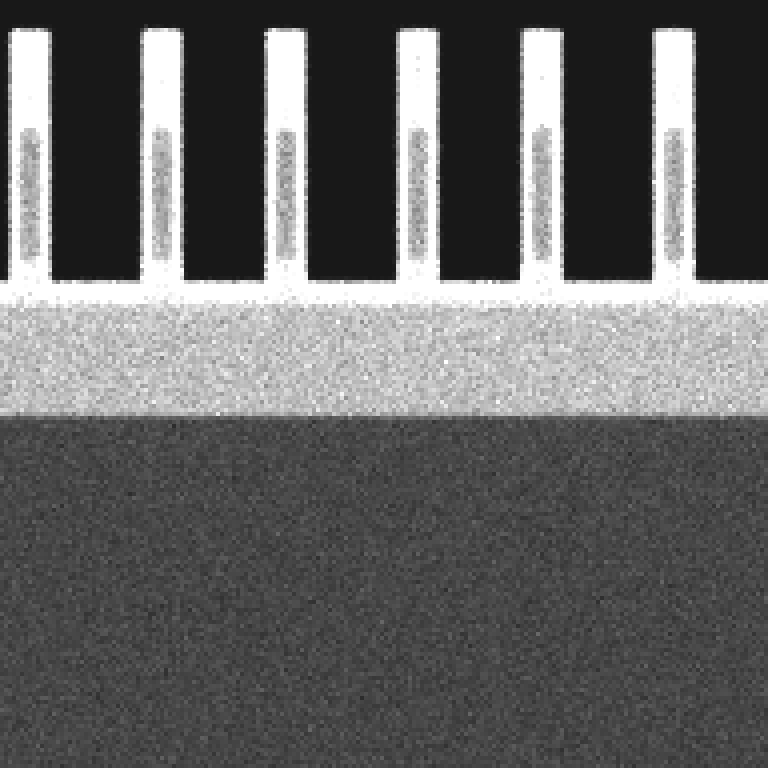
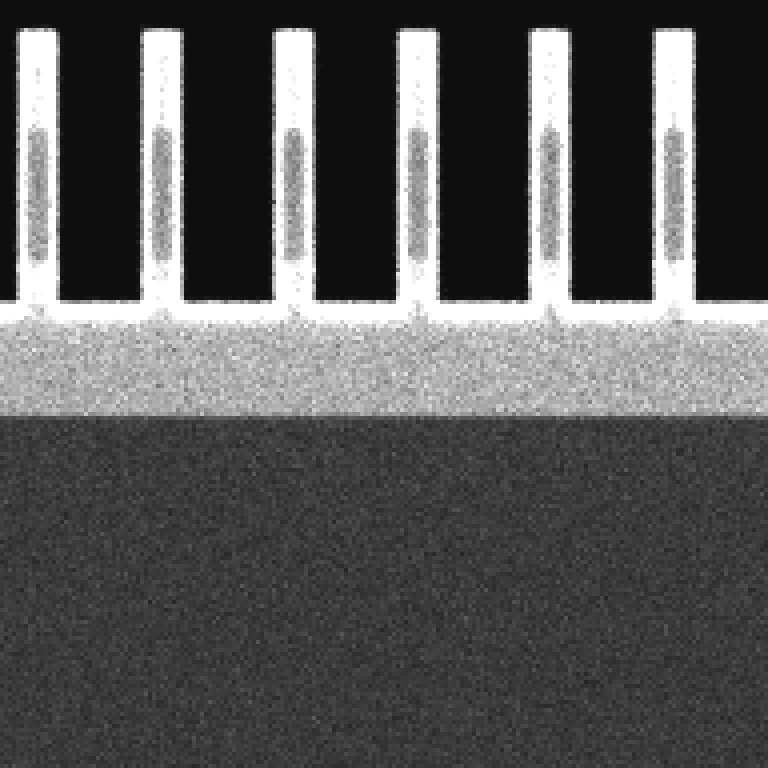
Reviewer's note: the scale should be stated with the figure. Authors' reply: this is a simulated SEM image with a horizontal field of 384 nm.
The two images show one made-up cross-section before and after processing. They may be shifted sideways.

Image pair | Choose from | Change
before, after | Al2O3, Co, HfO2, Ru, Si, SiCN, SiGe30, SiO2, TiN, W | Ru (removed)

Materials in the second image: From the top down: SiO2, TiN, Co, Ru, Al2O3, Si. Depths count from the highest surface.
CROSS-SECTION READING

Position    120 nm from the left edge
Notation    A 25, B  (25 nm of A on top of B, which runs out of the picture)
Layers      empty 136, Al2O3 56, Si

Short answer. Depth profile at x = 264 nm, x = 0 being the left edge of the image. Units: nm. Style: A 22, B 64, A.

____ empty 136, Al2O3 56, Si